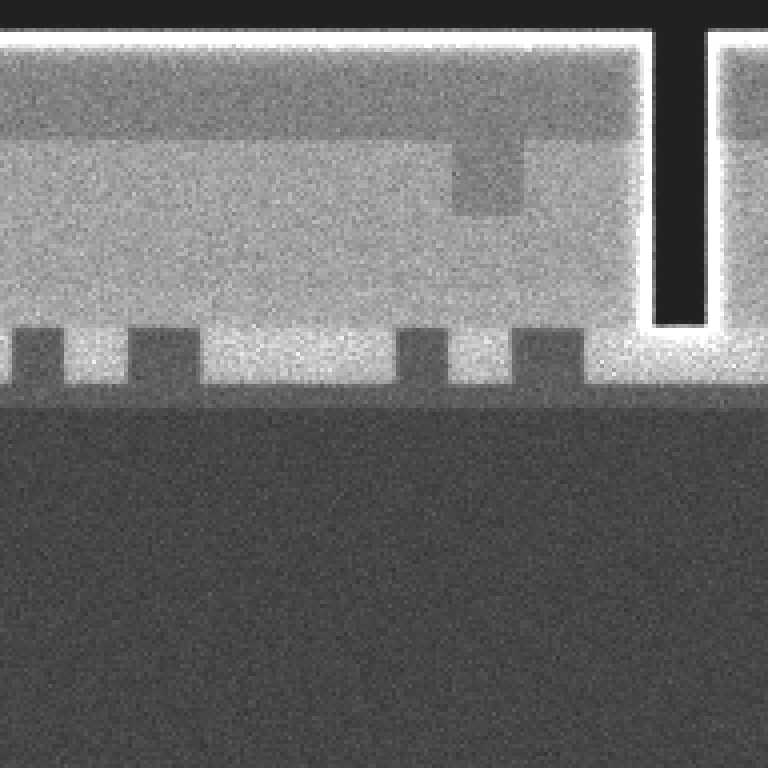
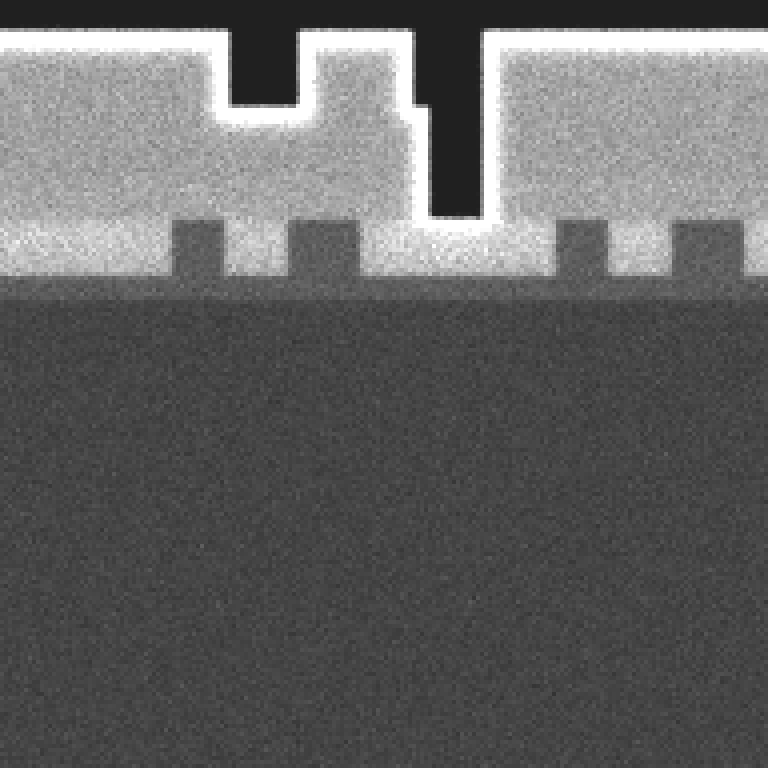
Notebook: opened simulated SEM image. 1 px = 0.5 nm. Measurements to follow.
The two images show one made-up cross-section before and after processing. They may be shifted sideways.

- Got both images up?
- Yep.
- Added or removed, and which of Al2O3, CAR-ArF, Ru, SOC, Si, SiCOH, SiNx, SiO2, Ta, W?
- removed, SOC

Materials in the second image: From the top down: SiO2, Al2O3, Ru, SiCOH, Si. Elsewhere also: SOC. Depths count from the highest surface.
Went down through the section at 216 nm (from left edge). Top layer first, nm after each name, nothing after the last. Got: empty 94, Ru 28, SiCOH 12, Si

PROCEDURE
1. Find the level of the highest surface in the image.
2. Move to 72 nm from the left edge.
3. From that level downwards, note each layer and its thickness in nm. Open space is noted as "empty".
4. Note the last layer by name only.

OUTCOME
SiO2 74, Al2O3 20, Ru 28, SiCOH 12, Si